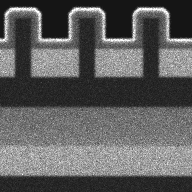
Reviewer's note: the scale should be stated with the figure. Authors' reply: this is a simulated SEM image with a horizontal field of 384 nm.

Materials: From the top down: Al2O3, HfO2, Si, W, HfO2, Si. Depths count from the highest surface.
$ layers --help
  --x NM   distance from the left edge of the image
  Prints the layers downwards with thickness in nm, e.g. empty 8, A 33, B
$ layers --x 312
Al2O3 20, Si 178, W 78, HfO2 60, Si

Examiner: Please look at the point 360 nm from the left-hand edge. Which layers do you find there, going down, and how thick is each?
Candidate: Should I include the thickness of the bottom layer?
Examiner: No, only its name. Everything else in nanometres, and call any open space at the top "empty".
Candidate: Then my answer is empty 62, Al2O3 20, HfO2 56, Si 60, W 78, HfO2 60, Si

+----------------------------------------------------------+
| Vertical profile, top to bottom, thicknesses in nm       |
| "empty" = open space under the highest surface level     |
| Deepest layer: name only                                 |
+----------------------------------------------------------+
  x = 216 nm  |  empty 62, Al2O3 20, HfO2 56, Si 60, W 78, HfO2 60, Si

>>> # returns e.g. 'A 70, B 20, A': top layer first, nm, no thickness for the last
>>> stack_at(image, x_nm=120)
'empty 62, Al2O3 20, HfO2 56, Si 60, W 78, HfO2 60, Si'